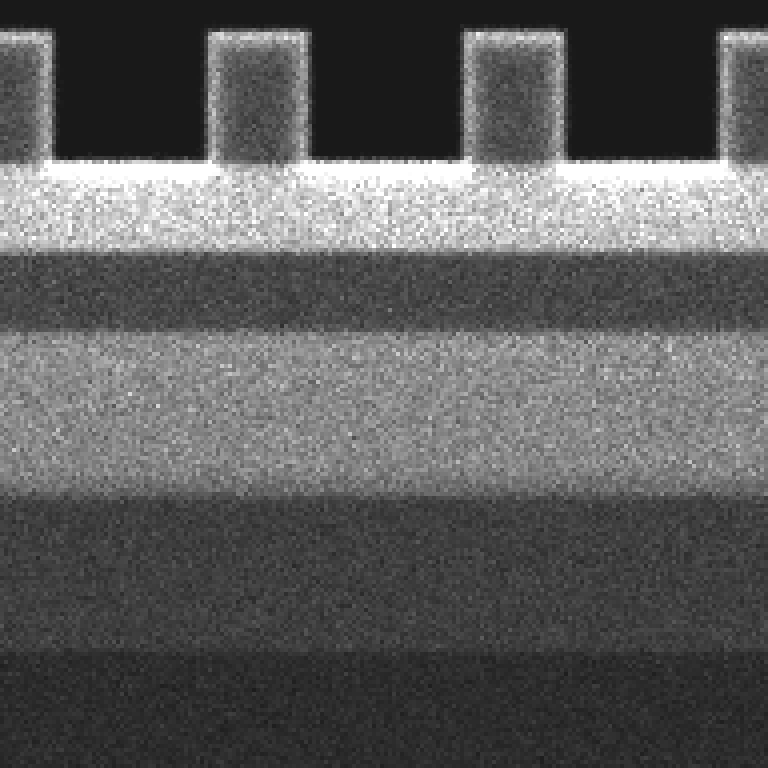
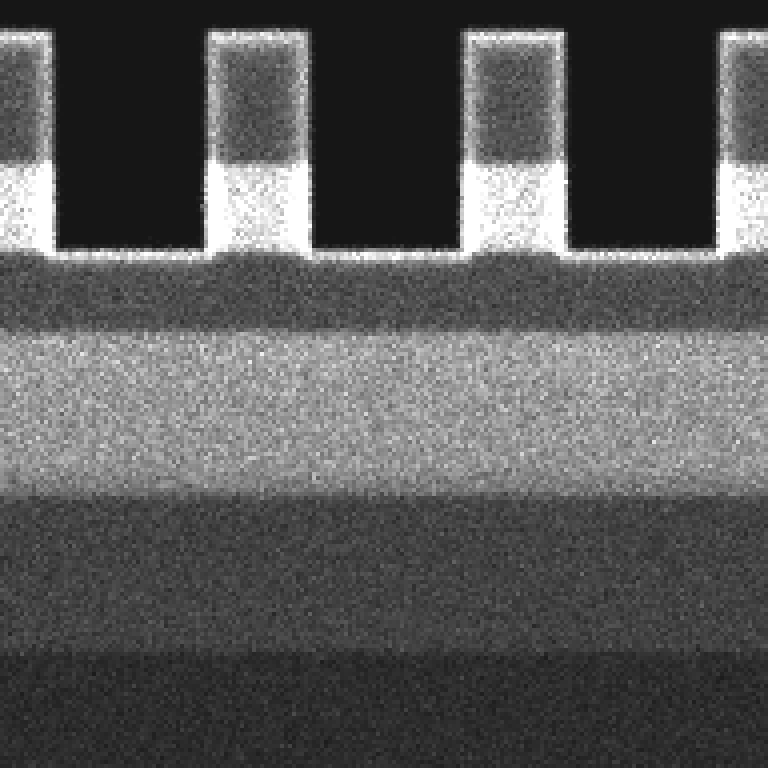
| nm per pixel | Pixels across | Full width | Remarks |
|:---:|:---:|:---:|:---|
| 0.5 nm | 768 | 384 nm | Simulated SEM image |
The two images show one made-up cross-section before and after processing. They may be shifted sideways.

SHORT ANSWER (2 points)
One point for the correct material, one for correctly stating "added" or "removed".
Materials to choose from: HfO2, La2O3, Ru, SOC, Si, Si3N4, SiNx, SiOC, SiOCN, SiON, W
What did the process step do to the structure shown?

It removed HfO2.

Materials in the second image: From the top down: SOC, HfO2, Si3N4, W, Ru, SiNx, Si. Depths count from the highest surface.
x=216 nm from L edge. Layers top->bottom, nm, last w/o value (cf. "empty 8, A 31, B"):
empty 110, Si3N4 40, W 72, Ru 10, SiNx 78, Si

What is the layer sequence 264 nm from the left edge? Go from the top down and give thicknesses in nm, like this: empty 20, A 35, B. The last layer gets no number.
SOC 66, HfO2 44, Si3N4 40, W 72, Ru 10, SiNx 78, Si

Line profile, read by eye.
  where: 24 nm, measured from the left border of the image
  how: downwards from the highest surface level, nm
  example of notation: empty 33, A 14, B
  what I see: SOC 66, HfO2 44, Si3N4 40, W 72, Ru 10, SiNx 78, Si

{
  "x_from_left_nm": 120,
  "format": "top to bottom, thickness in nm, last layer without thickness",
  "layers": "SOC 66, HfO2 44, Si3N4 40, W 72, Ru 10, SiNx 78, Si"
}